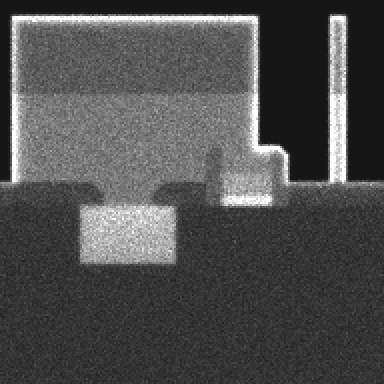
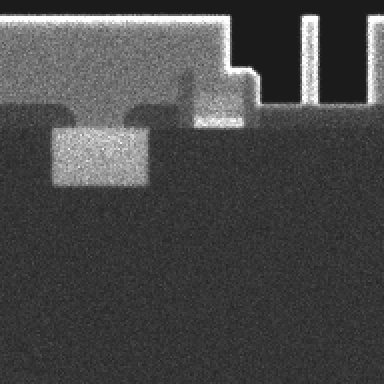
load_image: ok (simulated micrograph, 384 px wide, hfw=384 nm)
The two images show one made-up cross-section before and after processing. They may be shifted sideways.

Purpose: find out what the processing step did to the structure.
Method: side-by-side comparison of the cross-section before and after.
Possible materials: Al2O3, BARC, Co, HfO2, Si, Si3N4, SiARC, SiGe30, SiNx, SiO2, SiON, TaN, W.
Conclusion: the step removed SiARC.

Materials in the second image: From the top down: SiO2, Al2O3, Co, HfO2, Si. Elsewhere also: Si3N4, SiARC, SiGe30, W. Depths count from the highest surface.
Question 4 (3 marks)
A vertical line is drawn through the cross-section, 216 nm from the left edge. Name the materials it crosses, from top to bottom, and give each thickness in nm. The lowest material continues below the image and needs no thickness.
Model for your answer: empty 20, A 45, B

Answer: SiO2 52, Al2O3 28, Co 22, HfO2 10, Si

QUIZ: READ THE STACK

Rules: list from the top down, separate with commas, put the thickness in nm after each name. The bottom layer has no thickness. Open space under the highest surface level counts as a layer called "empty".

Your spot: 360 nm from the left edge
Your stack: empty 88, SiGe30 24, Si